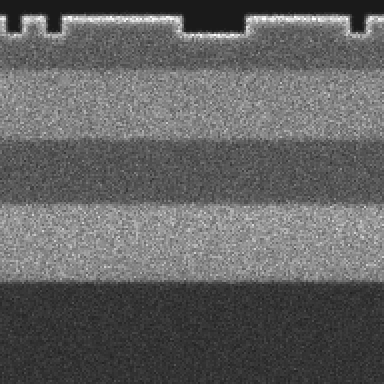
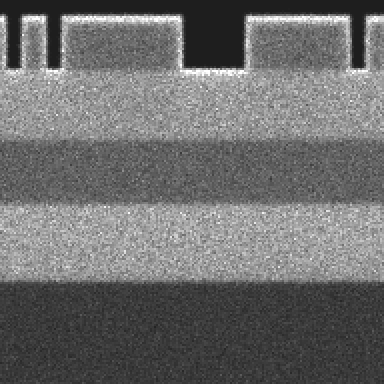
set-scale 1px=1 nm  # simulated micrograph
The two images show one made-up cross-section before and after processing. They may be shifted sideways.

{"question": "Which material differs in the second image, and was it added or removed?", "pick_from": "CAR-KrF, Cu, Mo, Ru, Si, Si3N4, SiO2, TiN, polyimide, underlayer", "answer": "TiN, removed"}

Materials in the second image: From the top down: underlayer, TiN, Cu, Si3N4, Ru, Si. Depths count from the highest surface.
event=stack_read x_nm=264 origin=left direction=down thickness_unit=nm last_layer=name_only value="underlayer 18, TiN 36, Cu 70, Si3N4 64, Ru 78, Si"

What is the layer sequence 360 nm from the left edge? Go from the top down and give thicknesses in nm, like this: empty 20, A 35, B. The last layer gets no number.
empty 54, Cu 70, Si3N4 64, Ru 78, Si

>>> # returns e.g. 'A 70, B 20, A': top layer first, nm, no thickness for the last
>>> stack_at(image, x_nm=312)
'underlayer 18, TiN 36, Cu 70, Si3N4 64, Ru 78, Si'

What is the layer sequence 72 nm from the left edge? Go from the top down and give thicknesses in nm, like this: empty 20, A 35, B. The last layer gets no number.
underlayer 18, TiN 36, Cu 70, Si3N4 64, Ru 78, Si